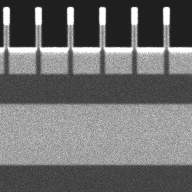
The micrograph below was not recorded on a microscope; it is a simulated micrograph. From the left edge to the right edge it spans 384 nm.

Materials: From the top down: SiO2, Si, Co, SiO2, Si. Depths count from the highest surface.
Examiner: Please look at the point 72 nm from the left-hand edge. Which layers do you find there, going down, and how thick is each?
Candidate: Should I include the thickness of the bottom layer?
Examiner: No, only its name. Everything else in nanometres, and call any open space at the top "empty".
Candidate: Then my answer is Si 192, Co 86, SiO2 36, Si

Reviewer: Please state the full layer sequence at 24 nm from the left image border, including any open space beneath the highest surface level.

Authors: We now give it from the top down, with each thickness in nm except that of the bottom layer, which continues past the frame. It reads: empty 80, SiO2 52, Si 60, Co 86, SiO2 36, Si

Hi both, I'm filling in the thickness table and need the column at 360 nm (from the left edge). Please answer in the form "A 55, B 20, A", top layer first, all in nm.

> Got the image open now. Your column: empty 80, SiO2 52, Si 60, Co 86, SiO2 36, Si